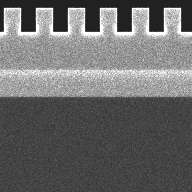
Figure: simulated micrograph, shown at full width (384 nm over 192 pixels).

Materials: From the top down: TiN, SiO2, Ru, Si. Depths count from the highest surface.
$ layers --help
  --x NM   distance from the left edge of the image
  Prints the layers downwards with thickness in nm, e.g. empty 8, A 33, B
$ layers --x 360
TiN 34, SiO2 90, Ru 54, Si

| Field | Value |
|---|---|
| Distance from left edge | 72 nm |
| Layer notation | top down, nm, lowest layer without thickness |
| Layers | TiN 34, SiO2 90, Ru 54, Si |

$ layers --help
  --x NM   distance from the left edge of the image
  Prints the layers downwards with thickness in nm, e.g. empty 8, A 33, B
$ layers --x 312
empty 48, SiO2 76, Ru 54, Si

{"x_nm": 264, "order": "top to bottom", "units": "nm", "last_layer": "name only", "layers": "TiN 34, SiO2 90, Ru 54, Si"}